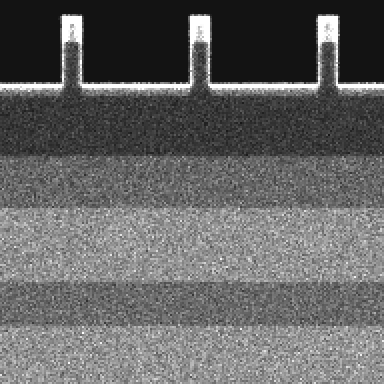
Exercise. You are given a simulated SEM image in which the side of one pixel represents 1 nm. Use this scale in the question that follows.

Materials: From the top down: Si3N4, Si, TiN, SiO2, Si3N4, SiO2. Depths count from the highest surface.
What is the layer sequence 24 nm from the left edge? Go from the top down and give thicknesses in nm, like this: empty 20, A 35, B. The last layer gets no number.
empty 68, Si3N4 12, Si 60, TiN 52, SiO2 74, Si3N4 44, SiO2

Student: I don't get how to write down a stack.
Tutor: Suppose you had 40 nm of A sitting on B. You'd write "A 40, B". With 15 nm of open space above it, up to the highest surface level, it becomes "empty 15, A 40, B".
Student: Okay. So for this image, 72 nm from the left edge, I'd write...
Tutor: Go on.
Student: SiO2 26, Si 114, TiN 52, SiO2 74, Si3N4 44, SiO2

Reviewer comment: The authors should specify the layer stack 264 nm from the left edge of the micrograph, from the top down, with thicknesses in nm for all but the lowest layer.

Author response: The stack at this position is empty 68, Si3N4 12, Si 60, TiN 52, SiO2 74, Si3N4 44, SiO2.